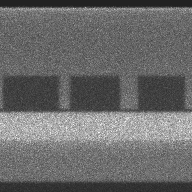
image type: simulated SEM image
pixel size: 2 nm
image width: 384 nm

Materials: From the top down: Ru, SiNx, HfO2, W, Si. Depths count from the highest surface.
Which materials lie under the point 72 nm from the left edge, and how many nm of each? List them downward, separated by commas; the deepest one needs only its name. Ru 136, SiNx 72, HfO2 56, W 84, Si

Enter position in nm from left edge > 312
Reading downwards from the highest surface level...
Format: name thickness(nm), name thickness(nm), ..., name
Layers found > Ru 136, SiNx 72, HfO2 56, W 84, Si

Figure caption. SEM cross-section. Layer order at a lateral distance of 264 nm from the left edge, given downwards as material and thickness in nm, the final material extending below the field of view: Ru 202, SiNx 6, HfO2 56, W 84, Si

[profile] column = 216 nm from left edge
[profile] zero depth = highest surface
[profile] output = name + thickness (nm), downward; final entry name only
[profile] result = Ru 136, SiNx 72, HfO2 56, W 84, Si